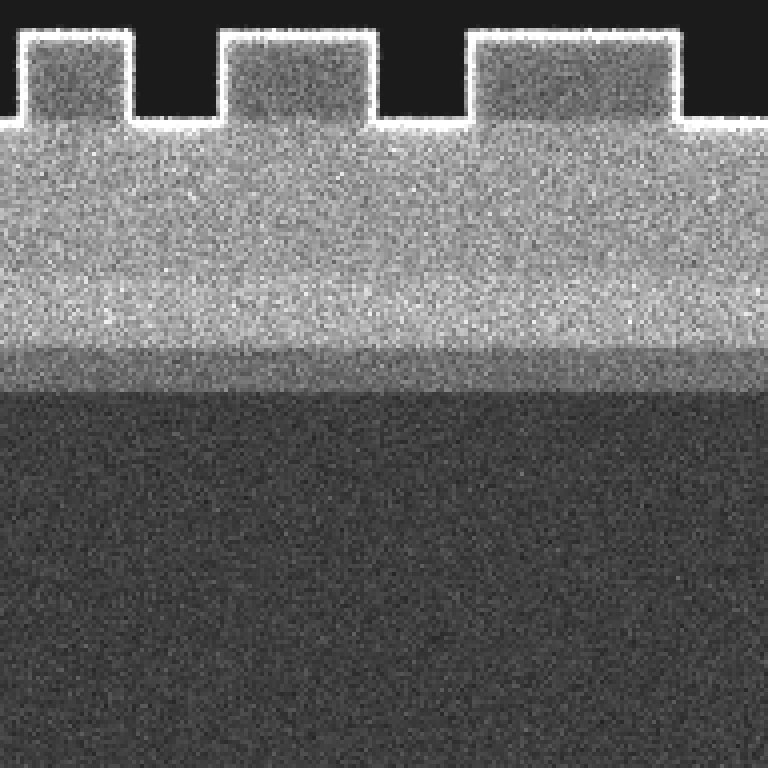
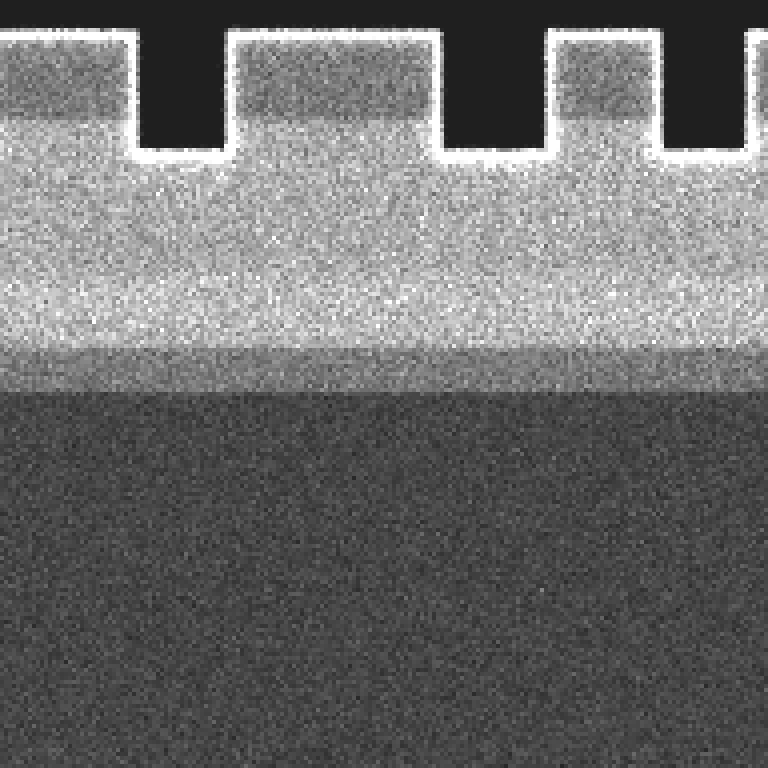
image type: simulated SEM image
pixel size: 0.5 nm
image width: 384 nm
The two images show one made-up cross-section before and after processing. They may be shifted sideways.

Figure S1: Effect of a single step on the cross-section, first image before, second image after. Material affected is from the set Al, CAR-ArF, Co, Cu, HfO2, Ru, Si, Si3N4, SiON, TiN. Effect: removed Co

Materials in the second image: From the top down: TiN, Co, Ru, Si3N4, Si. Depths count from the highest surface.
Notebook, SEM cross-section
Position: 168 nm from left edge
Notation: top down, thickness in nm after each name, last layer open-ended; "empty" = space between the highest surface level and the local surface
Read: TiN 44, Co 78, Ru 36, Si3N4 22, Si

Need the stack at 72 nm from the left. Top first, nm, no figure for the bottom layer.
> empty 60, Co 62, Ru 36, Si3N4 22, Si